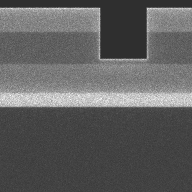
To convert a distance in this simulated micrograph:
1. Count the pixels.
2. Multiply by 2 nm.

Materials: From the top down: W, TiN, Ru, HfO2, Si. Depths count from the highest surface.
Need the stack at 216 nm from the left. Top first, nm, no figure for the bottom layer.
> empty 102, TiN 10, Ru 58, HfO2 28, Si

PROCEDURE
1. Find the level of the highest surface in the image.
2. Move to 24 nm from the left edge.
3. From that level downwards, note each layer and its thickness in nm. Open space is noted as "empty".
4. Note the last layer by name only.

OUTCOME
W 48, TiN 64, Ru 58, HfO2 28, Si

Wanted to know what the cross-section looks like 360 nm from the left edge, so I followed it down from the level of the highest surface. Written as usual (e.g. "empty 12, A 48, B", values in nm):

W 48, TiN 64, Ru 58, HfO2 28, Si